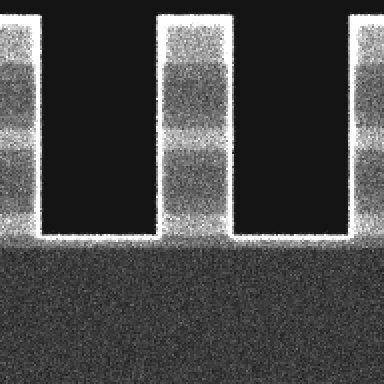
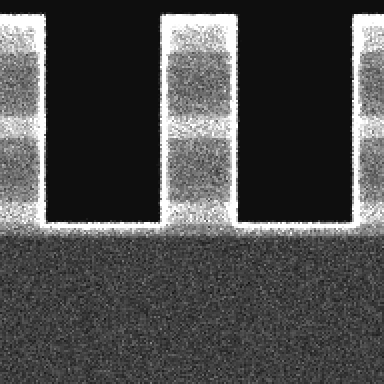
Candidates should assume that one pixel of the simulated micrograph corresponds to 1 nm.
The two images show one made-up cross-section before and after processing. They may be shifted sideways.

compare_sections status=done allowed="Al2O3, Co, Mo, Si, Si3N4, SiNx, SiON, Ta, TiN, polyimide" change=removed material="Al2O3"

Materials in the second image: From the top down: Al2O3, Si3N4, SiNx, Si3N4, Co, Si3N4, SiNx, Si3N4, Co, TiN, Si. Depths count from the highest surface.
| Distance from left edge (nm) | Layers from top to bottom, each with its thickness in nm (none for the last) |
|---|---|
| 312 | empty 208, TiN 12, Si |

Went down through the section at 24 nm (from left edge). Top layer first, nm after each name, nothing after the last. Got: Al2O3 36, Si3N4 16, SiNx 32, Si3N4 16, Co 22, Si3N4 16, SiNx 32, Si3N4 16, Co 22, TiN 12, Si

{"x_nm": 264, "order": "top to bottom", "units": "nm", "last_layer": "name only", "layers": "empty 208, TiN 12, Si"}